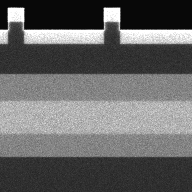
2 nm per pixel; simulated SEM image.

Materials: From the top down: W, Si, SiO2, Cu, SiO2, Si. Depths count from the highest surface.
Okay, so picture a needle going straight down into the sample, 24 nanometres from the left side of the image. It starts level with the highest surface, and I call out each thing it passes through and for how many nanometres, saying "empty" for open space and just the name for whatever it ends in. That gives W 28, Si 104, SiO2 54, Cu 66, SiO2 46, Si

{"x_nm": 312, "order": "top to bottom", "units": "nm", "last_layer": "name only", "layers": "empty 44, W 28, Si 60, SiO2 54, Cu 66, SiO2 46, Si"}